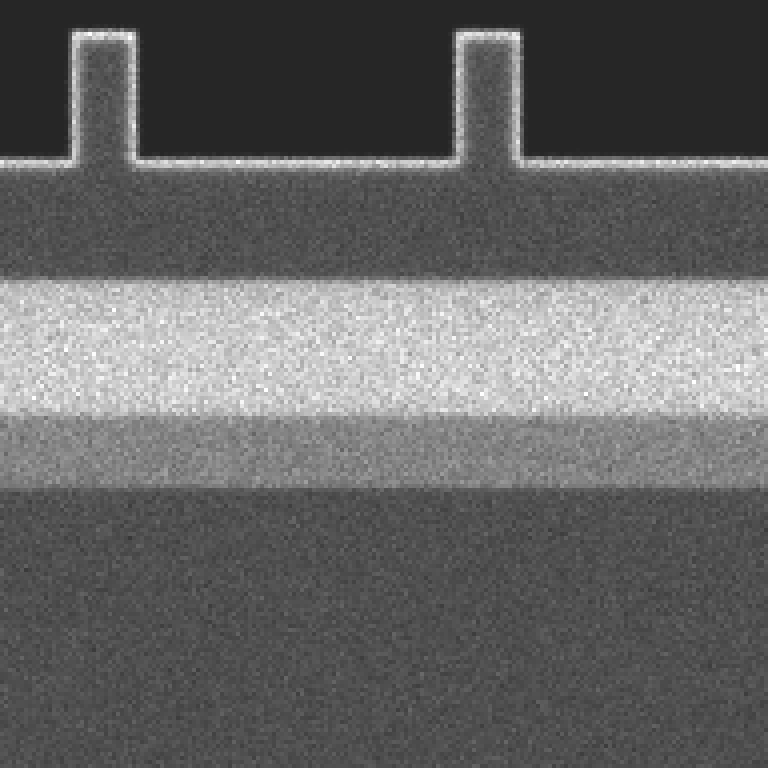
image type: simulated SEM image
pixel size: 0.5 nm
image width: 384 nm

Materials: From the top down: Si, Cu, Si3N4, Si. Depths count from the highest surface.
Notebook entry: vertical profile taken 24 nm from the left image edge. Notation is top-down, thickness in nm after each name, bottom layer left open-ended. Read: empty 64, Si 60, Cu 68, Si3N4 36, Si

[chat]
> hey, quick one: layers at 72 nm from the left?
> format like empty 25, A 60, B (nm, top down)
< empty 64, Si 60, Cu 68, Si3N4 36, Si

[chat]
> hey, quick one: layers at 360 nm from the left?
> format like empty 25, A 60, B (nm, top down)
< empty 64, Si 60, Cu 68, Si3N4 36, Si